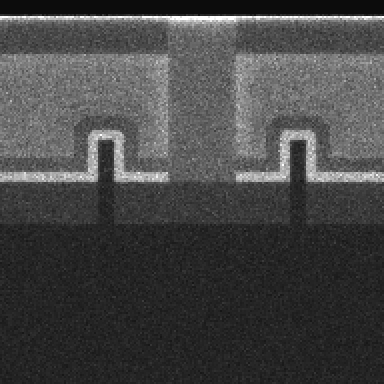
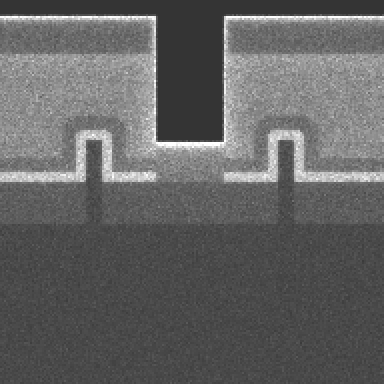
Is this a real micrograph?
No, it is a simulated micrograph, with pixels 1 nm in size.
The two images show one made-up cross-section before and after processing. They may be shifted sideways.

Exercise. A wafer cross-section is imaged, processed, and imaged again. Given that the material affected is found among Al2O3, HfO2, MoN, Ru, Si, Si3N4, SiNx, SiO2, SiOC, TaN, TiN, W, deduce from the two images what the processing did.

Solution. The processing removed Al2O3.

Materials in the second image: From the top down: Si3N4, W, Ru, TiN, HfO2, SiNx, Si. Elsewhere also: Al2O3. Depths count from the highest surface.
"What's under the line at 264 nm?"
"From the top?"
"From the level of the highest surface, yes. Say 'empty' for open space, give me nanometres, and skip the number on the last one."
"Si3N4 38, W 46, Ru 16, TiN 56, HfO2 10, SiNx 42, Si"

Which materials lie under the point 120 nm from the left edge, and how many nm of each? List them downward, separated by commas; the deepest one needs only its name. Si3N4 38, W 46, Ru 22, TiN 50, HfO2 10, SiNx 42, Si